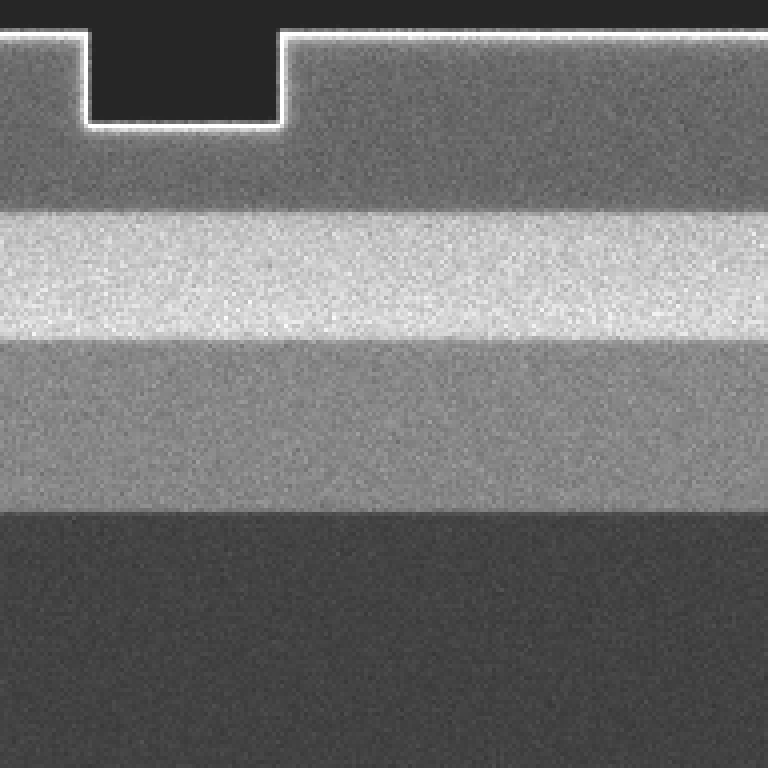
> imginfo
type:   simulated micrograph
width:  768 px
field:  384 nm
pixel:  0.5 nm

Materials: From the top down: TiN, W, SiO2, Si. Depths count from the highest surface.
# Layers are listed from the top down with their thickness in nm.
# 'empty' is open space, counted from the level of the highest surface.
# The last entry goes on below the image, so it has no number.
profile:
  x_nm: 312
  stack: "TiN 90, W 64, SiO2 86, Si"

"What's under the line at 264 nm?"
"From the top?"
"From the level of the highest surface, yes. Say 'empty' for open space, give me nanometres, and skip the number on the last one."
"TiN 90, W 64, SiO2 86, Si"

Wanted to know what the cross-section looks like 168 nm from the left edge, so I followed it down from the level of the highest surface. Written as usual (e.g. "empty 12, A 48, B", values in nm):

TiN 90, W 64, SiO2 86, Si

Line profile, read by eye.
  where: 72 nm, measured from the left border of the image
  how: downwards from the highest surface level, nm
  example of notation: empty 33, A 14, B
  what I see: empty 46, TiN 44, W 64, SiO2 86, Si